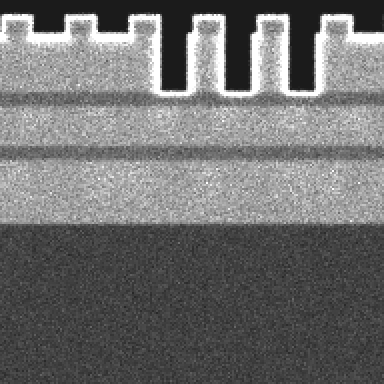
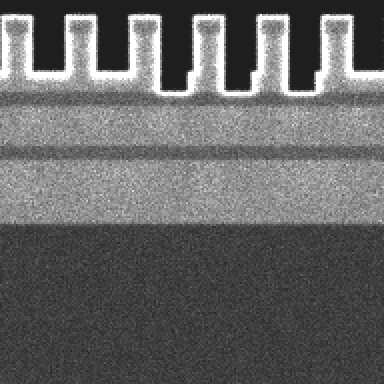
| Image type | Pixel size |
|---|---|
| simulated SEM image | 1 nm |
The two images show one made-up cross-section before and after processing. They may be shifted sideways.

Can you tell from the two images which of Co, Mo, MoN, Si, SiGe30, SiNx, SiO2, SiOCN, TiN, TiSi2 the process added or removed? Yes, it removed SiO2.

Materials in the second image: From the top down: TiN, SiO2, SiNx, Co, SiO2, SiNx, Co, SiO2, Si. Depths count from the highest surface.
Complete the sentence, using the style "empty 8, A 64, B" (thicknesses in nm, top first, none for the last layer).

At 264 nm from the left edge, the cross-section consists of TiN 18, SiO2 58, SiNx 14, SiO2 40, SiNx 14, SiO2 64, Si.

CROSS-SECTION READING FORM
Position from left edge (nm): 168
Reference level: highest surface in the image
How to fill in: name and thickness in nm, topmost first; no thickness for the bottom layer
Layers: empty 76, SiNx 14, Co 24, SiO2 16, SiNx 14, SiO2 64, Si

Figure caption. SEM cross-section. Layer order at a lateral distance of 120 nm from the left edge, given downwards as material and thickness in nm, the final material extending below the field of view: empty 56, SiO2 20, SiNx 14, SiO2 40, SiNx 14, Co 44, SiO2 20, Si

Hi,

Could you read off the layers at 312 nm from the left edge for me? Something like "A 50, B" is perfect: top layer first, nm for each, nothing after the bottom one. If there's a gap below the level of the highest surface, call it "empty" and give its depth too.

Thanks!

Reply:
empty 76, SiNx 14, SiO2 40, SiNx 14, Co 44, SiO2 20, Si